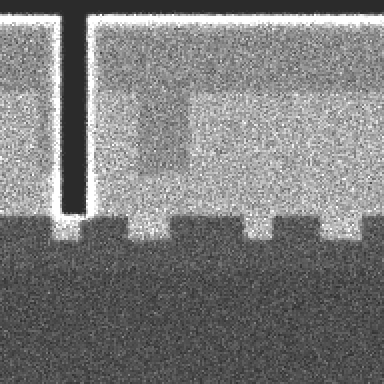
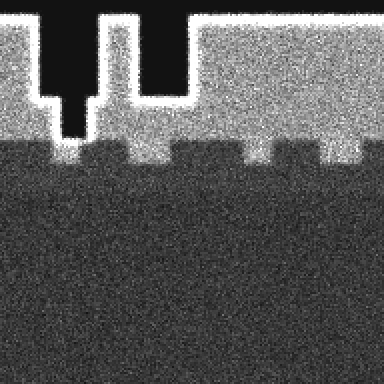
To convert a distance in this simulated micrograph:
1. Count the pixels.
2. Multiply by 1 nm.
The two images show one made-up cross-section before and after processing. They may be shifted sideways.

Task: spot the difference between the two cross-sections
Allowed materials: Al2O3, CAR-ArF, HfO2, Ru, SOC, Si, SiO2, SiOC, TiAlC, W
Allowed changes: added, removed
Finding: removed SOC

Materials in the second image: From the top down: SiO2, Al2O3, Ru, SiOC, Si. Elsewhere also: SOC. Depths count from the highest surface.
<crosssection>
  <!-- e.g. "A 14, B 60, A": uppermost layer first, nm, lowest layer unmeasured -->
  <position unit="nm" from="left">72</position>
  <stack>empty 124, Ru 24, SiOC 30, Si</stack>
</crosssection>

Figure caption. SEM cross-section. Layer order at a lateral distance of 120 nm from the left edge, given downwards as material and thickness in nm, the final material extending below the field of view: SiO2 116, Al2O3 8, SiOC 54, Si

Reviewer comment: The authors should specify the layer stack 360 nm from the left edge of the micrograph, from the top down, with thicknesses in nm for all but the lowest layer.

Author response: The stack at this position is SiO2 116, Al2O3 8, Ru 24, SiOC 30, Si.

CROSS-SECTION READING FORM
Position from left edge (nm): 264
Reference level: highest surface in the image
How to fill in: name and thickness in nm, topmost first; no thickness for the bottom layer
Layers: SiO2 116, Al2O3 8, Ru 24, SiOC 30, Si